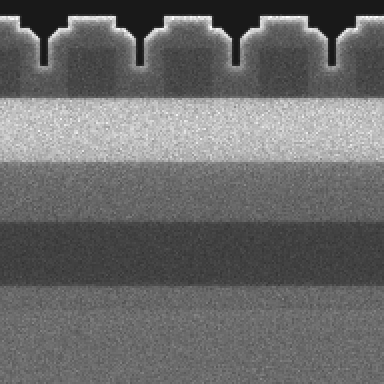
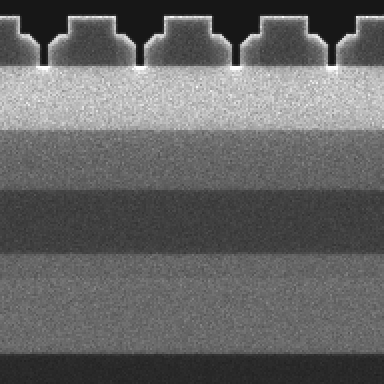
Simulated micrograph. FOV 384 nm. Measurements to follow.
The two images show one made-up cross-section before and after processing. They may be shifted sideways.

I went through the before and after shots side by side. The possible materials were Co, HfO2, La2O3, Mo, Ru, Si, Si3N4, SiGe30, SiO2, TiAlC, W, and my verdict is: removed, SiO2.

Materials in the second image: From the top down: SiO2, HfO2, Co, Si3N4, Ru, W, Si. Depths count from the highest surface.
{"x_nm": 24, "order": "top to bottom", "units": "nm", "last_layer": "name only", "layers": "empty 18, SiO2 32, HfO2 64, Co 60, Si3N4 64, Ru 24, W 76, Si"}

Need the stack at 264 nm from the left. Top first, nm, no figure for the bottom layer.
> Si3N4 50, HfO2 64, Co 60, Si3N4 64, Ru 24, W 76, Si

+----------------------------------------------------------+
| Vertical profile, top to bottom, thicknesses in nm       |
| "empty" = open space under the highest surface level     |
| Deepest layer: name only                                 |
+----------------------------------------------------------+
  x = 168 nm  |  Si3N4 50, HfO2 64, Co 60, Si3N4 64, Ru 24, W 76, Si